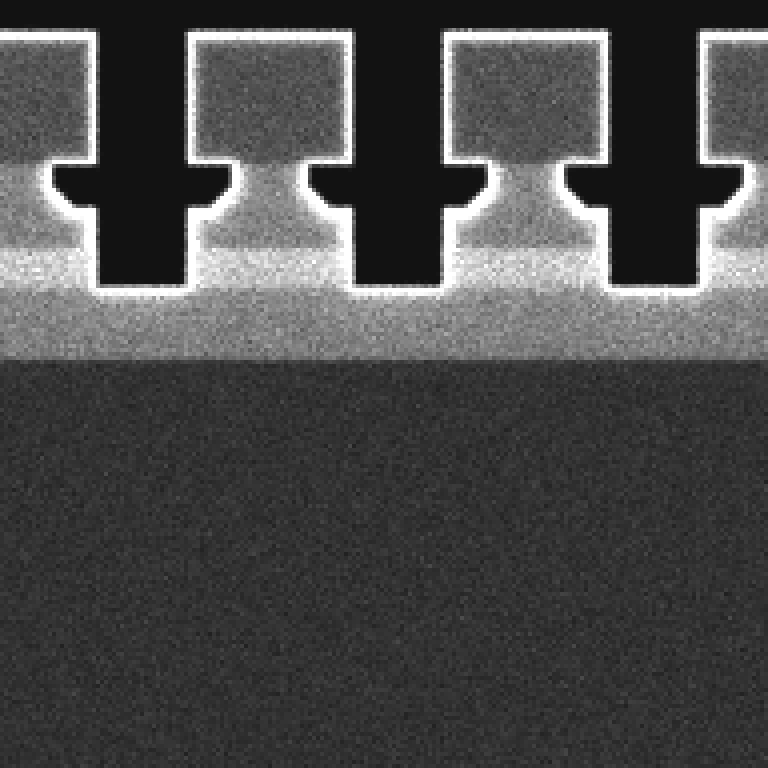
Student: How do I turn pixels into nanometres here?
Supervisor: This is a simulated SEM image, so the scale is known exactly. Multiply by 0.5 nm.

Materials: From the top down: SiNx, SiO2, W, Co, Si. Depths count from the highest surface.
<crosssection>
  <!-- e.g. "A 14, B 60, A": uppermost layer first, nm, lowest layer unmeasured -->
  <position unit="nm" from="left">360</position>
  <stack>SiNx 66, empty 22, SiO2 20, W 20, Co 36, Si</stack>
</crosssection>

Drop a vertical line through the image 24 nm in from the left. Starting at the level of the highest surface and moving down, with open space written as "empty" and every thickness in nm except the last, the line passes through SiNx 66, SiO2 42, W 20, Co 36, Si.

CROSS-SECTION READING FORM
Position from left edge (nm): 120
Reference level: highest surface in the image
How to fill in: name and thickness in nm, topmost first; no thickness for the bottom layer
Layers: SiNx 66, SiO2 42, W 20, Co 36, Si